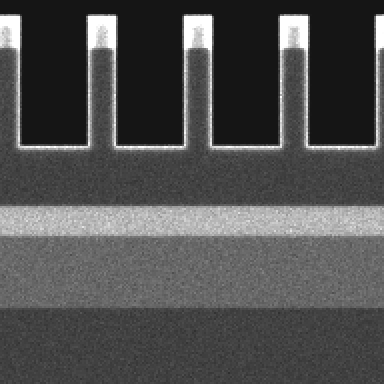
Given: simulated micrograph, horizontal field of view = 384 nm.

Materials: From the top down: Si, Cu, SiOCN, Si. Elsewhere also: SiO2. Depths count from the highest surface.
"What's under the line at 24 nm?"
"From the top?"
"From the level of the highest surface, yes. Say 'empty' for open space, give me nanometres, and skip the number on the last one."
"empty 130, Si 60, Cu 30, SiOCN 72, Si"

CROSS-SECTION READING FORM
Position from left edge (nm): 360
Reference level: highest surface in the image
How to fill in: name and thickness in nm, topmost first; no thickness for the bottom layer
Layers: empty 130, Si 60, Cu 30, SiOCN 72, Si